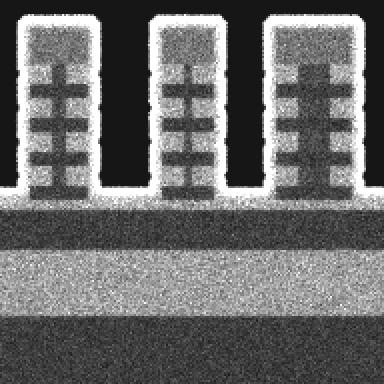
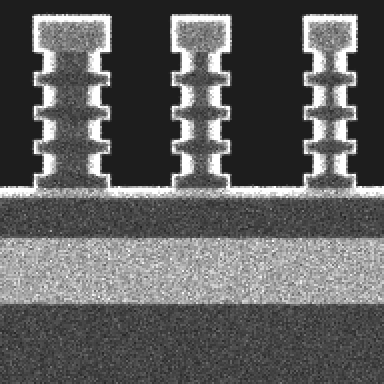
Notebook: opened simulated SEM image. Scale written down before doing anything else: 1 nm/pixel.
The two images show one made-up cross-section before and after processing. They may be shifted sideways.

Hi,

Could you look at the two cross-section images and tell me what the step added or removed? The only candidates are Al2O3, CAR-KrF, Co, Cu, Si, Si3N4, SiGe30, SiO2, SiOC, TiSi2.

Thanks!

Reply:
removed Al2O3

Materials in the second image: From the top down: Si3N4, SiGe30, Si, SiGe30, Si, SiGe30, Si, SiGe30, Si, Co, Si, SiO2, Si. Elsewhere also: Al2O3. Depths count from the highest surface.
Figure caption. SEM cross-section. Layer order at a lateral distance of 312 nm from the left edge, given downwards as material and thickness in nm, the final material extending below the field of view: Si3N4 36, empty 20, Si 14, empty 20, Si 14, empty 20, Si 14, empty 20, Si 14, Co 10, Si 40, SiO2 66, Si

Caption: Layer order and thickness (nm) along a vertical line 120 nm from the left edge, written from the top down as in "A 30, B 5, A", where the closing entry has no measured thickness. empty 172, Co 10, Si 40, SiO2 66, Si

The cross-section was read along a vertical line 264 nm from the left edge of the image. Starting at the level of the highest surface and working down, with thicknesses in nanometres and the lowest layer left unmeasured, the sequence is empty 172, Co 10, Si 40, SiO2 66, Si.